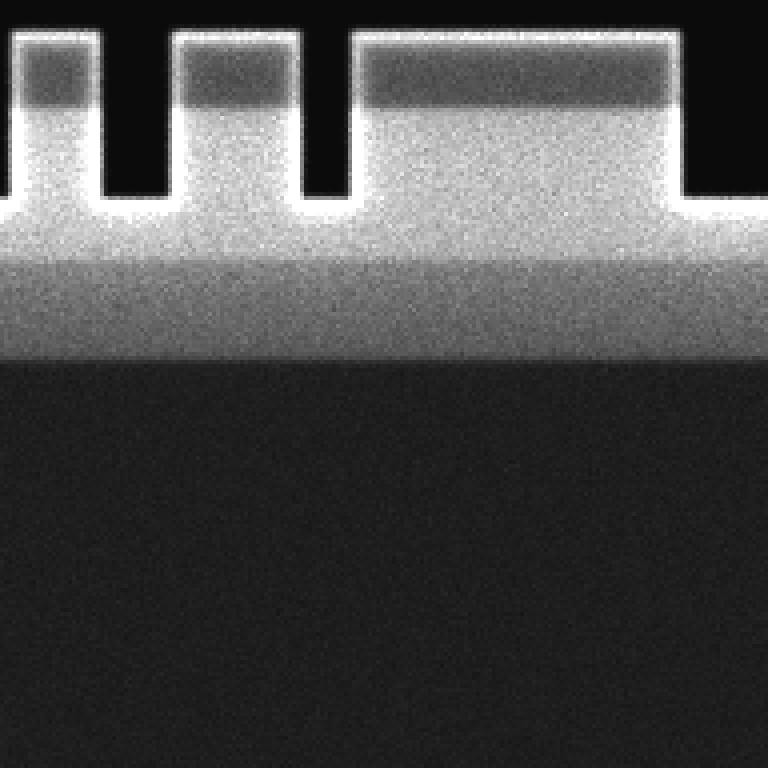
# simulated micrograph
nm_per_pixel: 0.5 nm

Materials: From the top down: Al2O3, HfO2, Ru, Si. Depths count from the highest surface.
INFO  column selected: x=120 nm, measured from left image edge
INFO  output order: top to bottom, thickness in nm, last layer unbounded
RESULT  Al2O3 38, HfO2 76, Ru 50, Si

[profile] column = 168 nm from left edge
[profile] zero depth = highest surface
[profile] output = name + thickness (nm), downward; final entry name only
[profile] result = empty 84, HfO2 30, Ru 50, Si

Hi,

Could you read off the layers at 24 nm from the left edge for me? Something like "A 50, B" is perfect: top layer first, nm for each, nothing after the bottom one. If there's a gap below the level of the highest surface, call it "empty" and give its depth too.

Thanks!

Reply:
Al2O3 38, HfO2 76, Ru 50, Si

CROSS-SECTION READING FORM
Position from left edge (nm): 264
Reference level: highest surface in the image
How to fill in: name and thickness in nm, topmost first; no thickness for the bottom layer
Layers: Al2O3 38, HfO2 76, Ru 50, Si